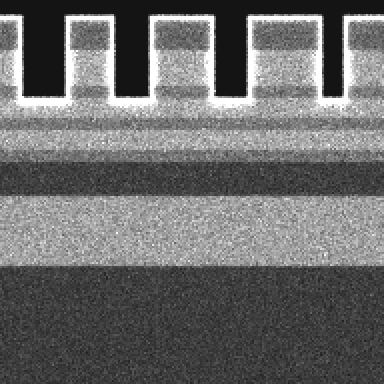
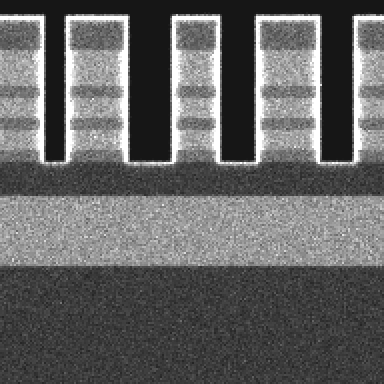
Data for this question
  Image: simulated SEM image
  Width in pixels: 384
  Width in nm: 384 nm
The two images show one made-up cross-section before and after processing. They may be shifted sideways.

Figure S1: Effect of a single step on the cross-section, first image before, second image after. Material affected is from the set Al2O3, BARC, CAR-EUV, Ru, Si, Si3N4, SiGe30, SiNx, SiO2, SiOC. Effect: removed Al2O3 and Si3N4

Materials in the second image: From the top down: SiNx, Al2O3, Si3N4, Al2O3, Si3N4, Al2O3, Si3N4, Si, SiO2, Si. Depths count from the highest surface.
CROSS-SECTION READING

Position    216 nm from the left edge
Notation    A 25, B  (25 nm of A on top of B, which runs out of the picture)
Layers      SiNx 34, Al2O3 36, Si3N4 12, Al2O3 20, Si3N4 12, Al2O3 20, Si3N4 12, Si 34, SiO2 70, Si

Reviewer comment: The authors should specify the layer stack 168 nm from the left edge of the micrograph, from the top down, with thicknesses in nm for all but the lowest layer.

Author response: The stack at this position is empty 146, Si 34, SiO2 70, Si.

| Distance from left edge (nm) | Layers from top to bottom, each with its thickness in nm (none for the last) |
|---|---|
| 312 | SiNx 34, Al2O3 36, Si3N4 12, Al2O3 20, Si3N4 12, Al2O3 20, Si3N4 12, Si 34, SiO2 70, Si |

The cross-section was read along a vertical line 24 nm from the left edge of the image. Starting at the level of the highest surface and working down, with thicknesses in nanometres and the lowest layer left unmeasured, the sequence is SiNx 34, Al2O3 36, Si3N4 12, Al2O3 20, Si3N4 12, Al2O3 20, Si3N4 12, Si 34, SiO2 70, Si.